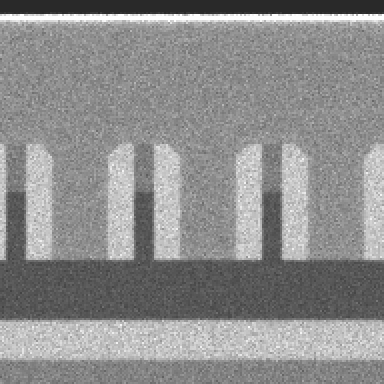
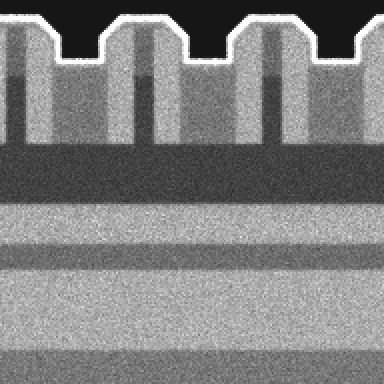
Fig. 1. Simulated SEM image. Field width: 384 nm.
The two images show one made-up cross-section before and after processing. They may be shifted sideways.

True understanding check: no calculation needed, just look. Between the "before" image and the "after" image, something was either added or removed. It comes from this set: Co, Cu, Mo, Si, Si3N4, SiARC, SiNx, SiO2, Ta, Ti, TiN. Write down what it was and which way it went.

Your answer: TiN (removed)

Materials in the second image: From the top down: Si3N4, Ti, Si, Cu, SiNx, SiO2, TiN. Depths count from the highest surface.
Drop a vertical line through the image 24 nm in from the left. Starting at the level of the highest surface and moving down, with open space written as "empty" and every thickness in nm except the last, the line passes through Si3N4 12, Ti 48, Si 128, Cu 40, SiNx 26, SiO2 80, TiN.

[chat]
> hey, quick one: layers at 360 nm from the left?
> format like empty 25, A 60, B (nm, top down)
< empty 16, Si3N4 112, Si 60, Cu 40, SiNx 26, SiO2 80, TiN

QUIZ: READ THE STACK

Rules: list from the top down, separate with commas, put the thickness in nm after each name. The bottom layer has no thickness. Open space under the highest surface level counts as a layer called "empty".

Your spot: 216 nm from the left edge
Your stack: empty 44, TiN 72, Si3N4 12, Si 60, Cu 40, SiNx 26, SiO2 80, TiN